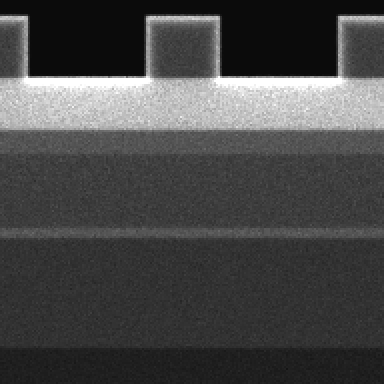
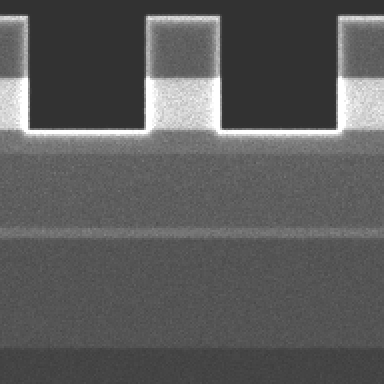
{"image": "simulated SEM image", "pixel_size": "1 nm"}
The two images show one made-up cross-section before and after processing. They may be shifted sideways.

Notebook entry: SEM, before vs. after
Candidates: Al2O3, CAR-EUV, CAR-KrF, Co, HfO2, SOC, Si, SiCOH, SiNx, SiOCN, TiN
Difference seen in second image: HfO2 removed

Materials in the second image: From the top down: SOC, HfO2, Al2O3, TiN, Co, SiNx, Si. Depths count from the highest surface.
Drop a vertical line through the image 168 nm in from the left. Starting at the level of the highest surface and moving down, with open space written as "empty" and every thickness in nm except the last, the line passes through SOC 62, HfO2 52, Al2O3 24, TiN 74, Co 10, SiNx 110, Si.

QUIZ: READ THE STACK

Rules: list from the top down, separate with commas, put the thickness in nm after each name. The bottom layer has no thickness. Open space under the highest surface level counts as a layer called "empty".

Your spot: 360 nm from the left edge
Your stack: SOC 62, HfO2 52, Al2O3 24, TiN 74, Co 10, SiNx 110, Si